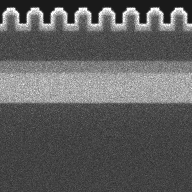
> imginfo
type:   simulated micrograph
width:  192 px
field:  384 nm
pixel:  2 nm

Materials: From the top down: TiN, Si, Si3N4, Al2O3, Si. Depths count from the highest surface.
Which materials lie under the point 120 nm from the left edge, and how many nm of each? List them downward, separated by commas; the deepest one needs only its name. TiN 14, Si 92, Si3N4 24, Al2O3 60, Si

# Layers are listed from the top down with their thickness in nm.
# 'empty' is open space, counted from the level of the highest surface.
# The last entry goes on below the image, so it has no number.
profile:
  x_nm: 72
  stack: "TiN 14, Si 92, Si3N4 24, Al2O3 60, Si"